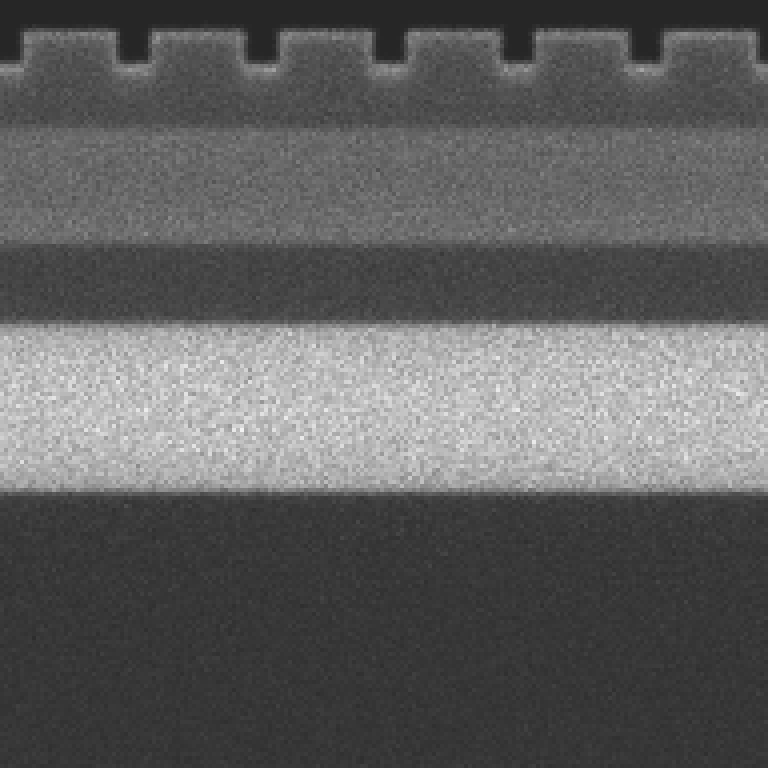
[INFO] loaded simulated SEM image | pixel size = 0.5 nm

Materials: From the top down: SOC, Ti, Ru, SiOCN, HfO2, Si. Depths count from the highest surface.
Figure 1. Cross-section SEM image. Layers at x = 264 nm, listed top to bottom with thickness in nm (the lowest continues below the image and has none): empty 16, SOC 12, Ti 20, Ru 58, SiOCN 40, HfO2 84, Si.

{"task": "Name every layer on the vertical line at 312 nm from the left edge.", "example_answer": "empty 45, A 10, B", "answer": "Ti 48, Ru 58, SiOCN 40, HfO2 84, Si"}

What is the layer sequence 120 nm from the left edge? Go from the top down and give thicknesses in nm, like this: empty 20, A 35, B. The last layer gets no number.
Ti 48, Ru 58, SiOCN 40, HfO2 84, Si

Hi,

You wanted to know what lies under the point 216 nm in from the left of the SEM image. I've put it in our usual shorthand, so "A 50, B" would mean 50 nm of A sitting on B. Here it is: Ti 48, Ru 58, SiOCN 40, HfO2 84, Si